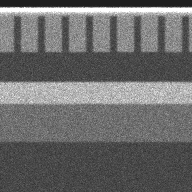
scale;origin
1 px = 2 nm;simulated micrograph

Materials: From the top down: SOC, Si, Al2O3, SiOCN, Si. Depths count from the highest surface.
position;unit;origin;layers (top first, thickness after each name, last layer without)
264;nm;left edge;SOC 88, Si 60, Al2O3 44, SiOCN 76, Si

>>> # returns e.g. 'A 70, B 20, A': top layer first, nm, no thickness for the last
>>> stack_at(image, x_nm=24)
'SOC 88, Si 60, Al2O3 44, SiOCN 76, Si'